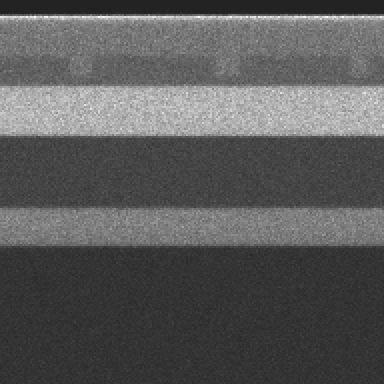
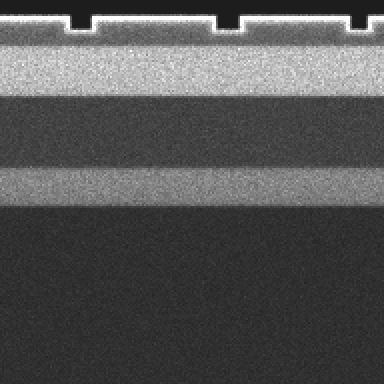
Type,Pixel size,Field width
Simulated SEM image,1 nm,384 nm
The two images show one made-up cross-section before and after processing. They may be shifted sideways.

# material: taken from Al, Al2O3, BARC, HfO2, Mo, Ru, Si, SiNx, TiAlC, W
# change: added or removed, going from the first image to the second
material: Ru
change: removed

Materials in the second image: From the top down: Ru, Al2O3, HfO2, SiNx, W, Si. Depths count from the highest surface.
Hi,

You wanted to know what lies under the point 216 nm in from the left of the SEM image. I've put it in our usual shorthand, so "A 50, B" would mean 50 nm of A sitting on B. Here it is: empty 14, Ru 6, Al2O3 10, HfO2 50, SiNx 72, W 38, Si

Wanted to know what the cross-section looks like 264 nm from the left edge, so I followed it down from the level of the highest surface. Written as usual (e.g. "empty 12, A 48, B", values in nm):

Al2O3 30, HfO2 50, SiNx 72, W 38, Si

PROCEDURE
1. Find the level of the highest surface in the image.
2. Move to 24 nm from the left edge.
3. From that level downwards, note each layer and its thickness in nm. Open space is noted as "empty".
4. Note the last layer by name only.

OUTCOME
Al2O3 30, HfO2 50, SiNx 72, W 38, Si